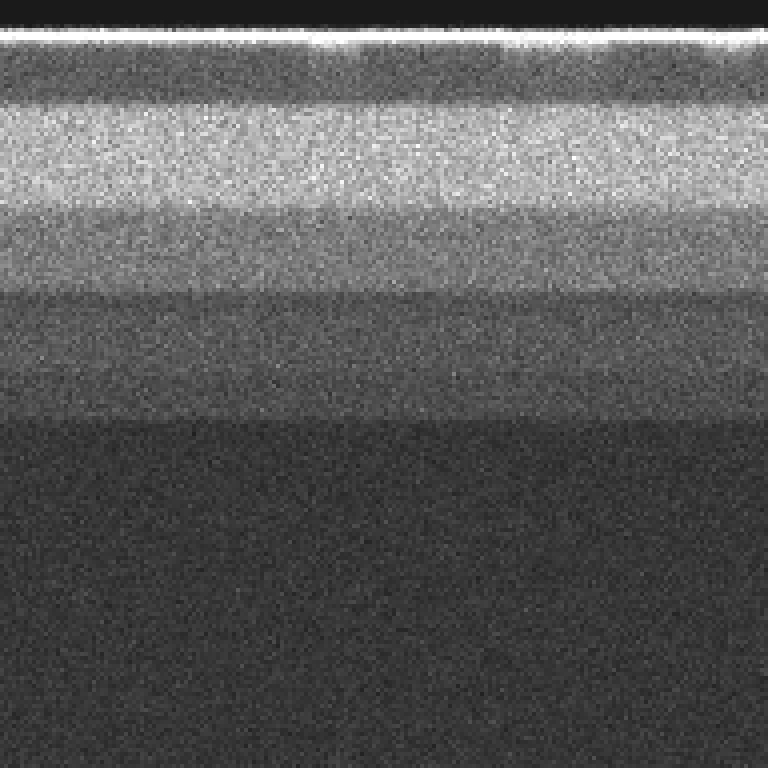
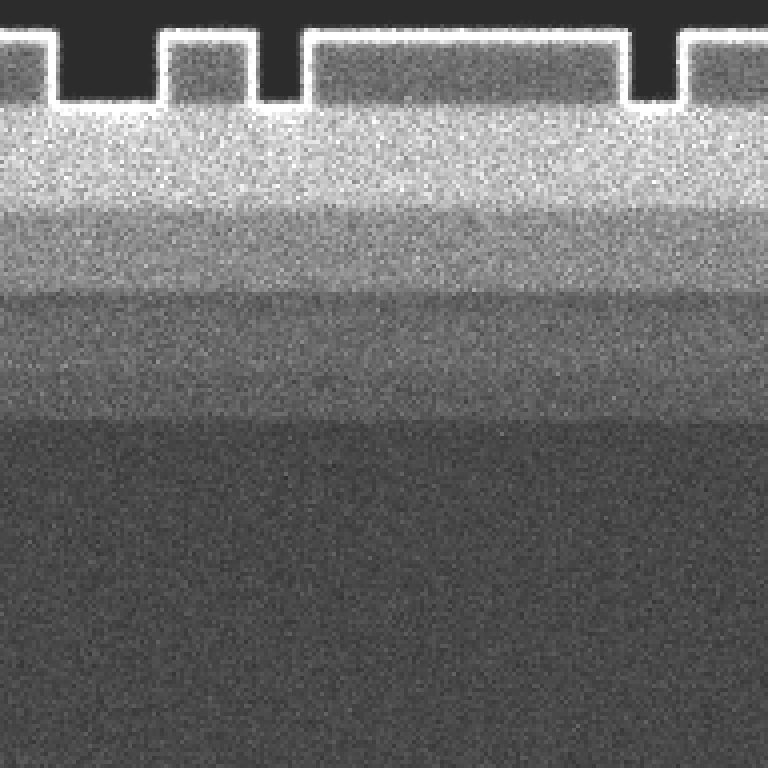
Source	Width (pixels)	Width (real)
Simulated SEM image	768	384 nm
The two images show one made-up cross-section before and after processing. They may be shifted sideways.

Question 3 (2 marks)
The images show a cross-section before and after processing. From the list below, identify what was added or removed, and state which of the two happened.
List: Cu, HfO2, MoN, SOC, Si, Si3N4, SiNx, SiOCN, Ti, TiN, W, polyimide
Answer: SOC was removed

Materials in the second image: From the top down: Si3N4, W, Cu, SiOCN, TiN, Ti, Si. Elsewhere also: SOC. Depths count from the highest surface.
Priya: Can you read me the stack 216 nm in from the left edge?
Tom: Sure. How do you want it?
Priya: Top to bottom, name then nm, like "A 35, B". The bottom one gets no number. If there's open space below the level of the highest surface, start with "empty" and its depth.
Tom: Si3N4 36, W 52, Cu 42, SiOCN 10, TiN 30, Ti 24, Si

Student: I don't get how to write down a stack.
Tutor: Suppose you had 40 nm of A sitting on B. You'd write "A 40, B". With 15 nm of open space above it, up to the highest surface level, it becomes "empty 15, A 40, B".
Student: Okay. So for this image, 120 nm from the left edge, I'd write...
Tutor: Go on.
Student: Si3N4 36, W 52, Cu 42, SiOCN 10, TiN 30, Ti 24, Si